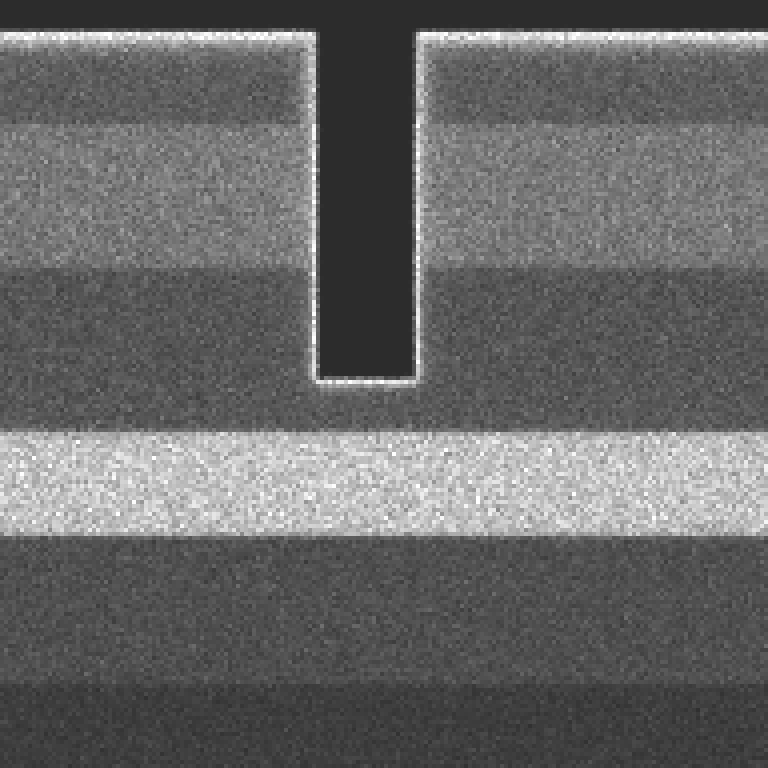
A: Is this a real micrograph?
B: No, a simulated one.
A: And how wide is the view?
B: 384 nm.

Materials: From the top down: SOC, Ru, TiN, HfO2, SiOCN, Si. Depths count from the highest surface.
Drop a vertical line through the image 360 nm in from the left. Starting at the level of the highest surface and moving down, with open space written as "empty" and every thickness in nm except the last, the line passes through SOC 46, Ru 72, TiN 82, HfO2 52, SiOCN 74, Si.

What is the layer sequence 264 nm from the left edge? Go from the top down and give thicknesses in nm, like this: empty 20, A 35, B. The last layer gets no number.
SOC 46, Ru 72, TiN 82, HfO2 52, SiOCN 74, Si